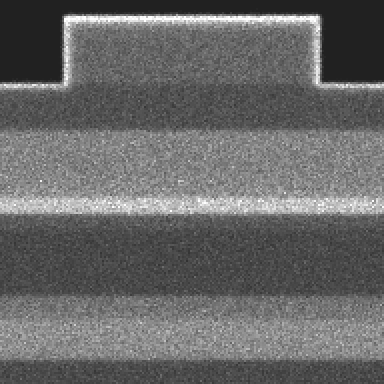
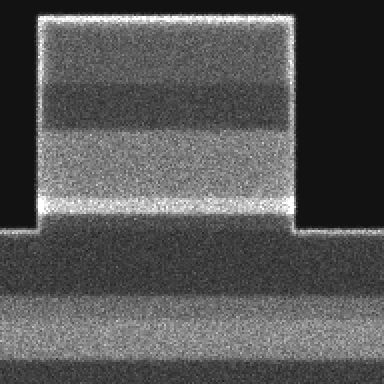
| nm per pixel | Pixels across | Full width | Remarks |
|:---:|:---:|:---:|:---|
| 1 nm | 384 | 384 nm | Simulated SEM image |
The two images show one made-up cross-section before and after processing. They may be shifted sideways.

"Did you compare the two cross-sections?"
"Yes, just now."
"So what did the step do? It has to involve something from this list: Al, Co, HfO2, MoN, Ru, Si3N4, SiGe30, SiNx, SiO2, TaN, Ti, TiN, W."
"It removed HfO2 and Ru and Si3N4 and TiN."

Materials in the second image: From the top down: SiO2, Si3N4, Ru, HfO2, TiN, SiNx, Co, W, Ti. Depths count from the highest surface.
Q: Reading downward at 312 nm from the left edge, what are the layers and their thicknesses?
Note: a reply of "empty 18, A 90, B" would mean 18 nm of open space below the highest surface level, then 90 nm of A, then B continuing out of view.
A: empty 214, SiNx 66, Co 24, W 40, Ti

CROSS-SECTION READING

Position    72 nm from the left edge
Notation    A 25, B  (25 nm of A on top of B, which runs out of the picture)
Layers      SiO2 68, Si3N4 46, Ru 68, HfO2 16, TiN 16, SiNx 66, Co 24, W 40, Ti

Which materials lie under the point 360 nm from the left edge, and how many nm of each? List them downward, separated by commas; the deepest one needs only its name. empty 214, SiNx 66, Co 24, W 40, Ti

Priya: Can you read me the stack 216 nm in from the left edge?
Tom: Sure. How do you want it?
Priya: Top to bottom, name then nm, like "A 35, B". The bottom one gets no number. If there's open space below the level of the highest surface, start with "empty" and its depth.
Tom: SiO2 68, Si3N4 46, Ru 68, HfO2 16, TiN 16, SiNx 66, Co 24, W 40, Ti